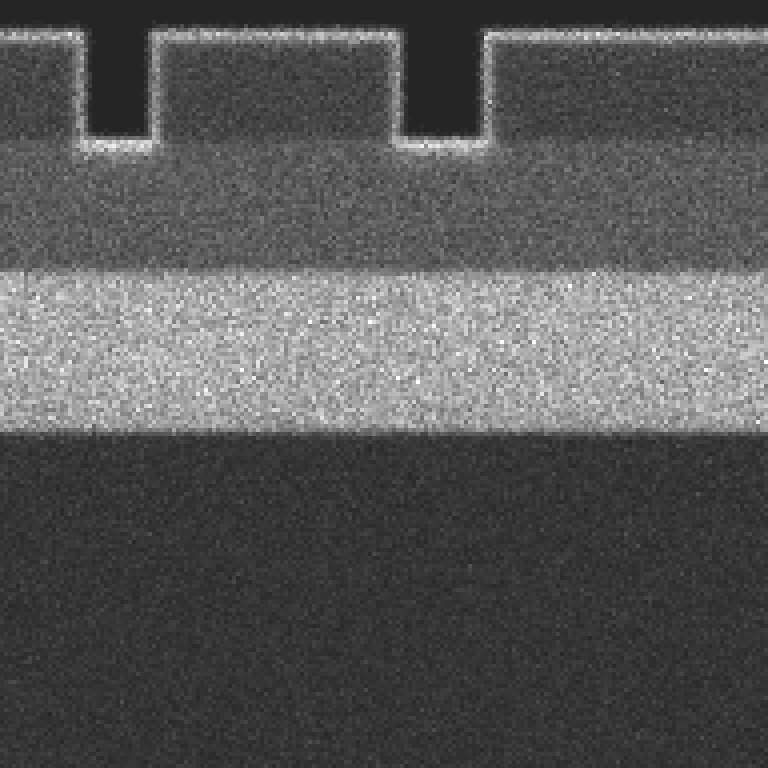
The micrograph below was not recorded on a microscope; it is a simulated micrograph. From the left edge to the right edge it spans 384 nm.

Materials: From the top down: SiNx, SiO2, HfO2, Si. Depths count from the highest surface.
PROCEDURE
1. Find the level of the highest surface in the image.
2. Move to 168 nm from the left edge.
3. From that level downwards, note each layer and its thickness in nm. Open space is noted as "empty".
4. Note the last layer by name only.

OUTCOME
SiNx 54, SiO2 66, HfO2 80, Si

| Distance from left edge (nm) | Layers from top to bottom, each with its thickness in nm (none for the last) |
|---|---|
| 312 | SiNx 54, SiO2 66, HfO2 80, Si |